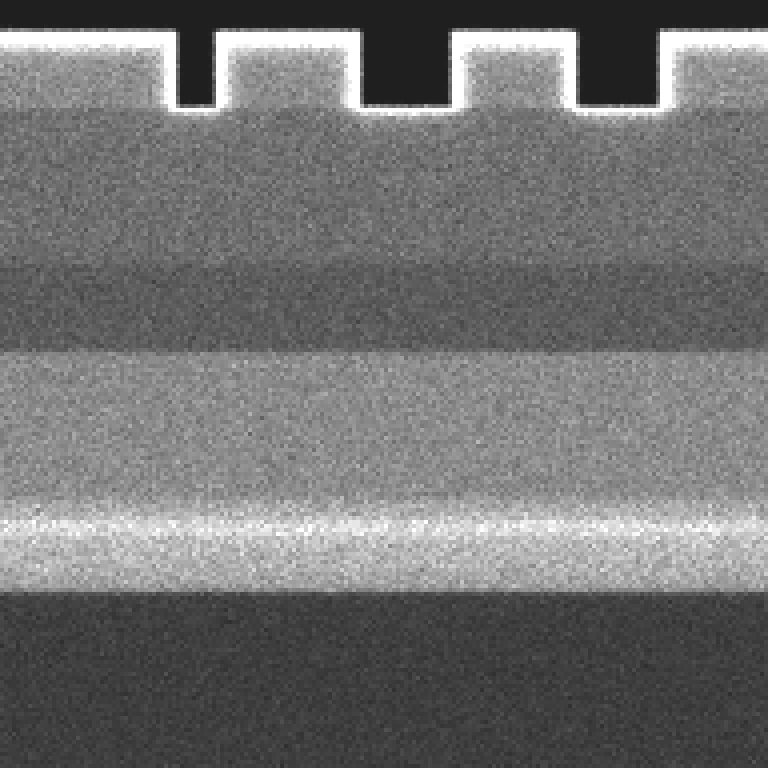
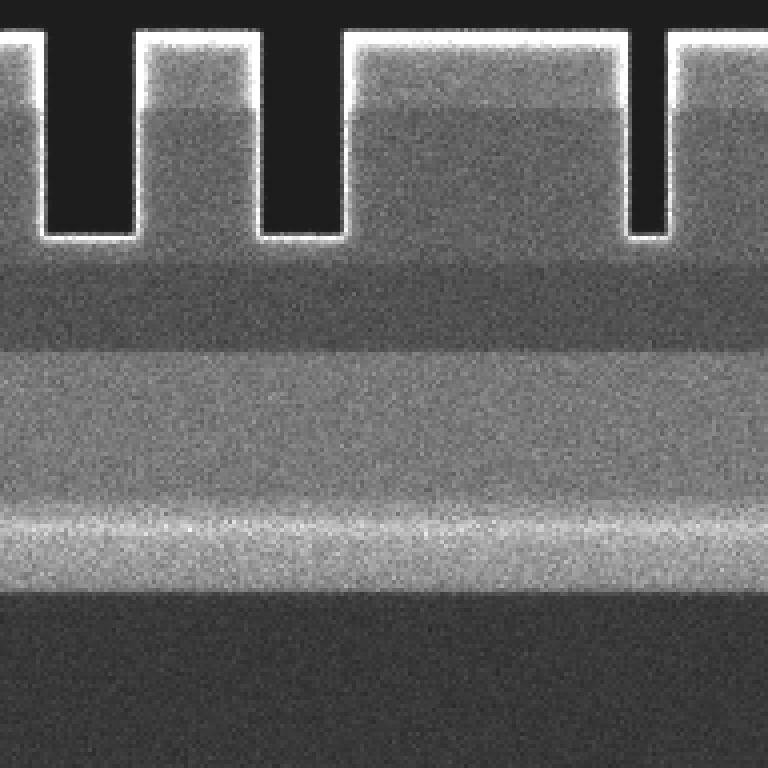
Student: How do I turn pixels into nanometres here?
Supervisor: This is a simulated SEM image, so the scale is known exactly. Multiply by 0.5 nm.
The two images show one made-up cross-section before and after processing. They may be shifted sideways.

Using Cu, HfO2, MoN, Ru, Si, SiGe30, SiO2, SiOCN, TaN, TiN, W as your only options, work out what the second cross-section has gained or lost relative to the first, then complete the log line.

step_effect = removed TiN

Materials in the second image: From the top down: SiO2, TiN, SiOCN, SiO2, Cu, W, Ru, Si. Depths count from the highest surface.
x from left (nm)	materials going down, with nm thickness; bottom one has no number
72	SiO2 38, TiN 78, SiOCN 44, SiO2 74, Cu 10, W 8, Ru 28, Si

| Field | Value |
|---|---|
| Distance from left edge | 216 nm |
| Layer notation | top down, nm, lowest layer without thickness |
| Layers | SiO2 38, TiN 78, SiOCN 44, SiO2 74, Cu 10, W 8, Ru 28, Si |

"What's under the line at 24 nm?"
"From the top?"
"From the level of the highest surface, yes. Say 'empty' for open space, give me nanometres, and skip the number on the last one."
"empty 102, TiN 14, SiOCN 44, SiO2 74, Cu 10, W 8, Ru 28, Si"